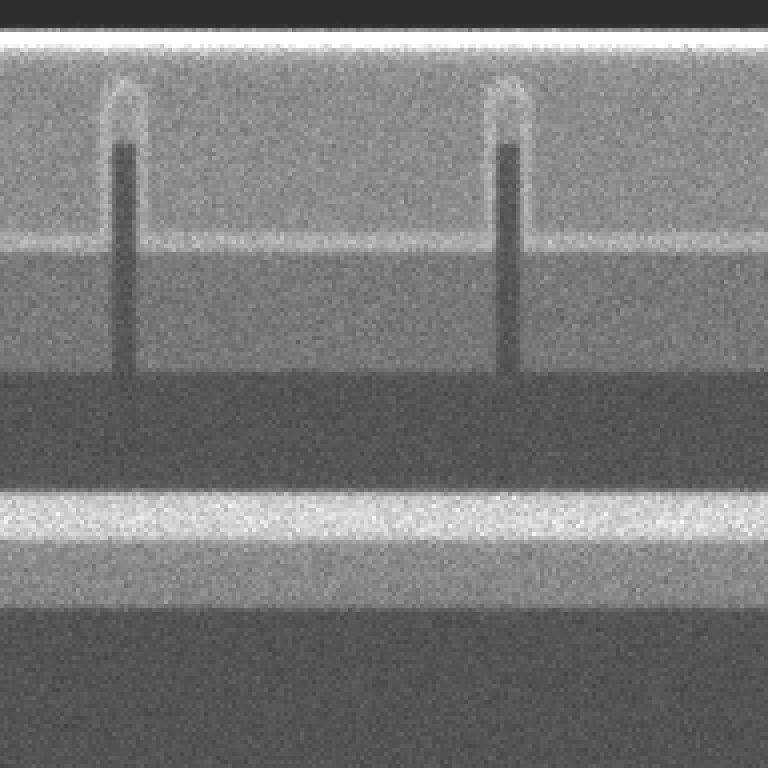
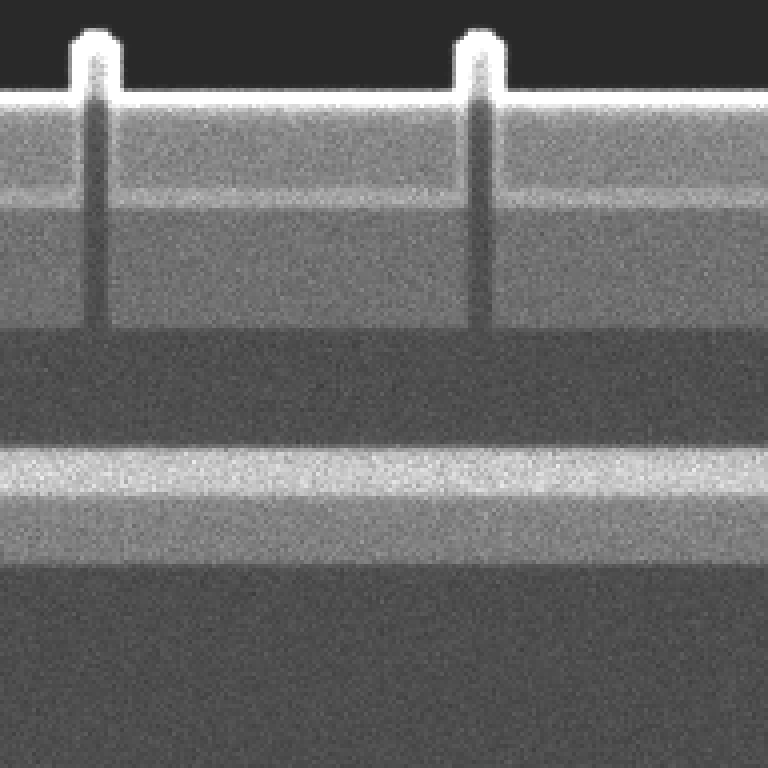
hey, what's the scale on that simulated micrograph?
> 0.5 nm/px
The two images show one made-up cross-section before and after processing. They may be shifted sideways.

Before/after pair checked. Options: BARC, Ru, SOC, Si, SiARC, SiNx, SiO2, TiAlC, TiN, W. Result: removed SOC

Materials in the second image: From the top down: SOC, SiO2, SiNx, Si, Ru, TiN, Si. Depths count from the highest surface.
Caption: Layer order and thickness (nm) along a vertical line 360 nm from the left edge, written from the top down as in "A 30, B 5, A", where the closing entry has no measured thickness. empty 30, SOC 48, SiO2 10, SiNx 60, Si 60, Ru 24, TiN 34, Si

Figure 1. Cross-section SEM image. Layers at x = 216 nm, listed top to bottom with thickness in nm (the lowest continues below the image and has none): empty 30, SOC 48, SiO2 10, SiNx 60, Si 60, Ru 24, TiN 34, Si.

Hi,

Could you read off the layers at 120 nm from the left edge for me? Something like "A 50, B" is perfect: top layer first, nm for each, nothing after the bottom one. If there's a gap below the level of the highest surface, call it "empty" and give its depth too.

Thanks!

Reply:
empty 30, SOC 48, SiO2 10, SiNx 60, Si 60, Ru 24, TiN 34, Si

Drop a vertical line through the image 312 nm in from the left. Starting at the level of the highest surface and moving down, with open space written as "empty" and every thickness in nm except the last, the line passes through empty 30, SOC 48, SiO2 10, SiNx 60, Si 60, Ru 24, TiN 34, Si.